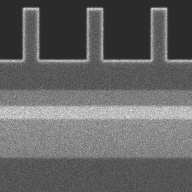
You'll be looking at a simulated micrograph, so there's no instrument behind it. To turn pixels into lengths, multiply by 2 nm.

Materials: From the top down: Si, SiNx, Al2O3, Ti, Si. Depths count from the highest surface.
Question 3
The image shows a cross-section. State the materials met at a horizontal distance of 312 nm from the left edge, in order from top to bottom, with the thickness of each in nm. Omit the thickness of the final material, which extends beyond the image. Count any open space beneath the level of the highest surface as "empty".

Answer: Si 164, SiNx 32, Al2O3 26, Ti 78, Si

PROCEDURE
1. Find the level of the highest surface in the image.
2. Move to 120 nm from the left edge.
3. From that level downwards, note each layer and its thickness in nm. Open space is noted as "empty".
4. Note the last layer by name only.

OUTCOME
empty 104, Si 60, SiNx 32, Al2O3 26, Ti 78, Si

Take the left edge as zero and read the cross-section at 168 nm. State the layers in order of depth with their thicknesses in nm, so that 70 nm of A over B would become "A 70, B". empty 104, Si 60, SiNx 32, Al2O3 26, Ti 78, Si